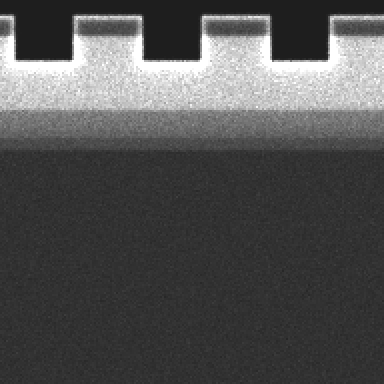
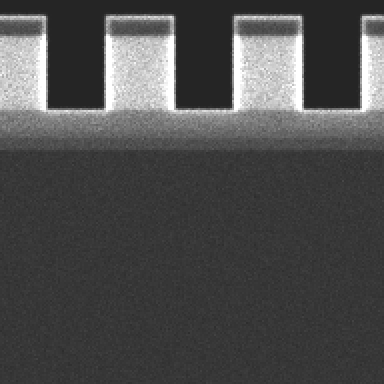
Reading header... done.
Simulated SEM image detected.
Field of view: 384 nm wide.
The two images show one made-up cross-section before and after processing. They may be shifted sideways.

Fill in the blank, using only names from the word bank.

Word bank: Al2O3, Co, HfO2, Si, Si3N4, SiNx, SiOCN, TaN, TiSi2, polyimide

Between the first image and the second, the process removed HfO2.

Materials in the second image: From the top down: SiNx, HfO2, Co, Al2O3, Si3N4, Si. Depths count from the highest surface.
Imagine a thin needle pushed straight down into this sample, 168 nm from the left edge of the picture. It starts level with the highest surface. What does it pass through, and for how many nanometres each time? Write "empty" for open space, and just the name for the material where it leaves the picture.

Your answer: SiNx 20, HfO2 74, Co 20, Al2O3 8, Si3N4 12, Si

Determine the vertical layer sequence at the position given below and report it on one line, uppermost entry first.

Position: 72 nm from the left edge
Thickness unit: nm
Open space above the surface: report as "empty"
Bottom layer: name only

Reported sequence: empty 94, Co 20, Al2O3 8, Si3N4 12, Si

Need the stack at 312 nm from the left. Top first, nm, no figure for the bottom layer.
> empty 94, Co 20, Al2O3 8, Si3N4 12, Si